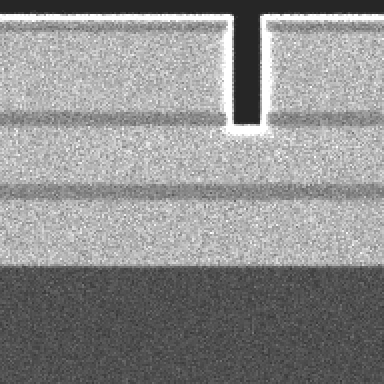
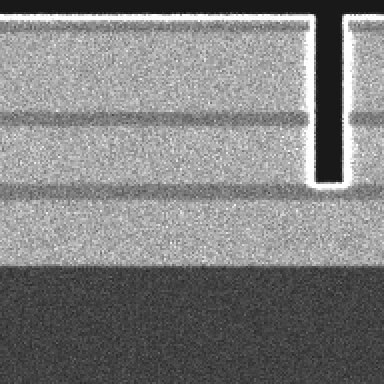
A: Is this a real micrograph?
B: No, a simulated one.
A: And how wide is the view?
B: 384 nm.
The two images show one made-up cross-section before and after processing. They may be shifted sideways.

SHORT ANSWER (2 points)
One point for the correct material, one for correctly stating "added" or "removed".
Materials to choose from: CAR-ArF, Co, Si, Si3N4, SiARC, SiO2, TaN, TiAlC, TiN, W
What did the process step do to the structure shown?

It removed SiO2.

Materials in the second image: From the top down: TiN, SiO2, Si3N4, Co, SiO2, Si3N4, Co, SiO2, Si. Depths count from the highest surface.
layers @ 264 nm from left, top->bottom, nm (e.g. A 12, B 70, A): TiN 16, SiO2 80, Si3N4 14, SiO2 58, Si3N4 16, SiO2 66, Si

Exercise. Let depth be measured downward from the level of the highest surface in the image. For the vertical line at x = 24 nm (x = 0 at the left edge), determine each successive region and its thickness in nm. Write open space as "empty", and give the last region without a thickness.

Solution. TiN 16, SiO2 80, Si3N4 14, Co 36, SiO2 22, Si3N4 16, SiO2 66, Si